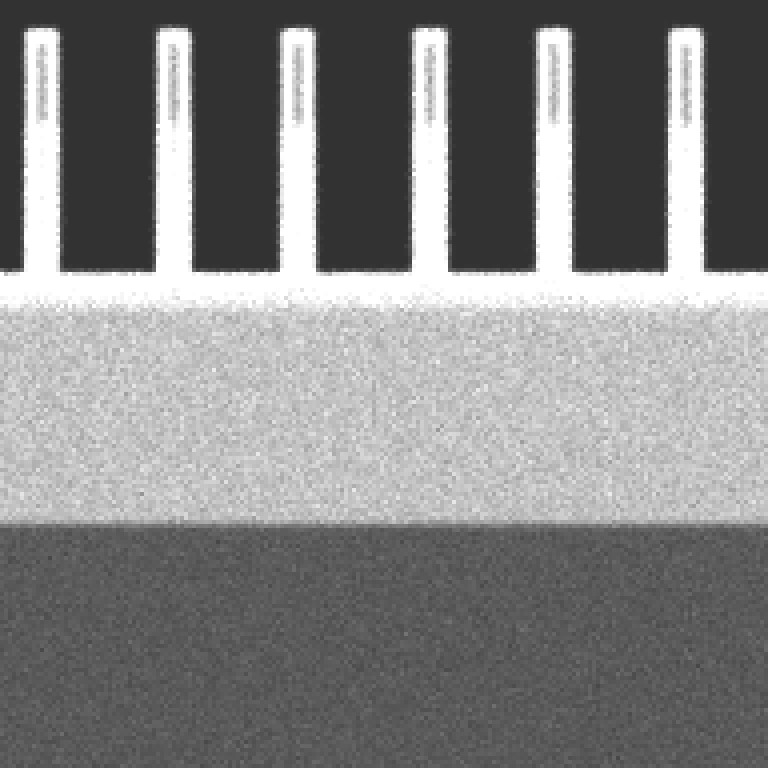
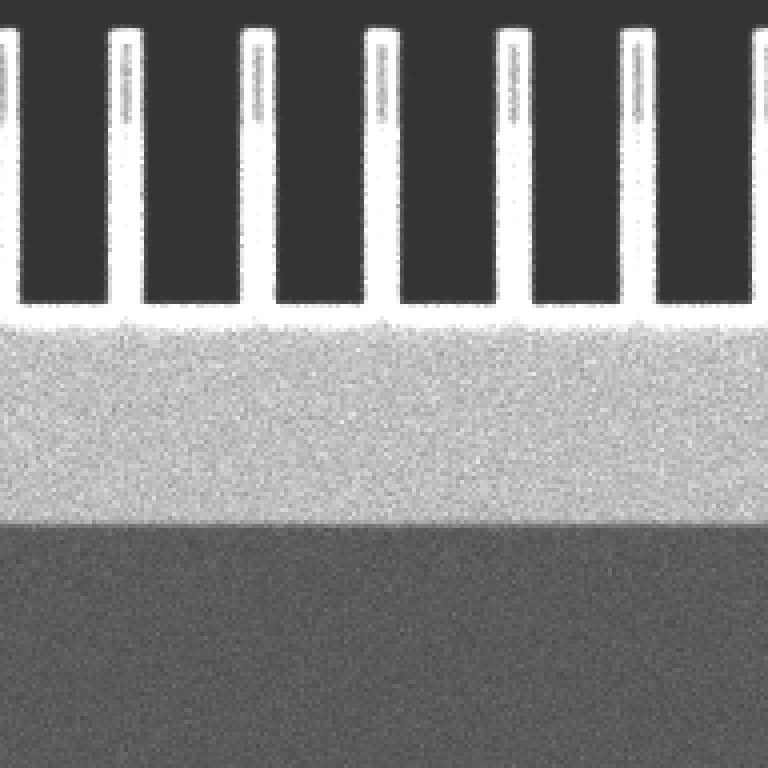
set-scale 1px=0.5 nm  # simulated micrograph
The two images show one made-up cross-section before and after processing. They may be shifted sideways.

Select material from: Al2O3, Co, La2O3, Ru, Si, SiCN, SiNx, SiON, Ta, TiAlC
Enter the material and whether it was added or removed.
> Ru / removed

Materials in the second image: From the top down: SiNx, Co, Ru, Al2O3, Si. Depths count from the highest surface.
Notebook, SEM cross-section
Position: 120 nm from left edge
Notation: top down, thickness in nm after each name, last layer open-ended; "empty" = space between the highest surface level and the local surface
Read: empty 138, Al2O3 108, Si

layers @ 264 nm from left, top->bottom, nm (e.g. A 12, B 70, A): empty 138, Al2O3 108, Si